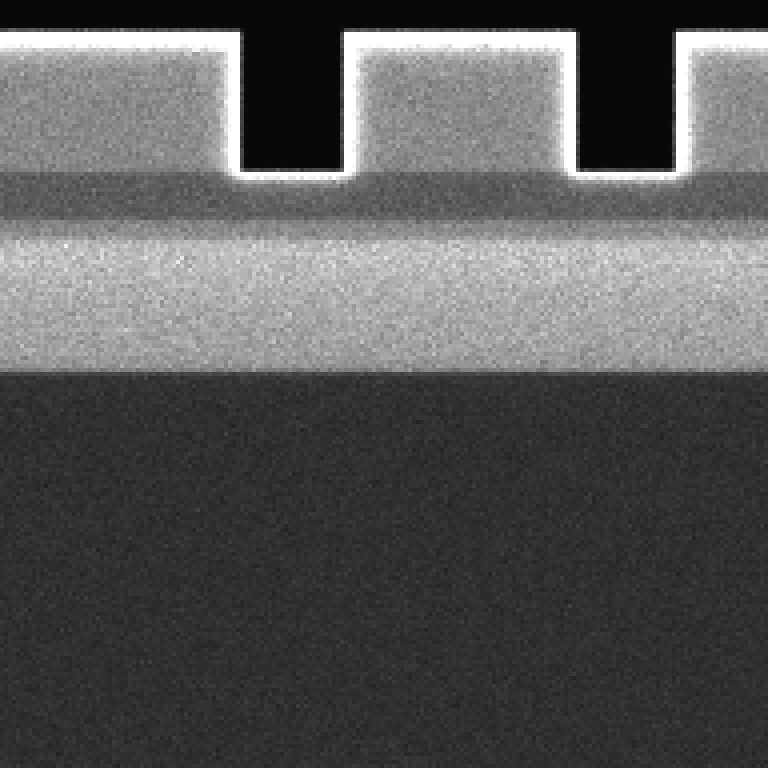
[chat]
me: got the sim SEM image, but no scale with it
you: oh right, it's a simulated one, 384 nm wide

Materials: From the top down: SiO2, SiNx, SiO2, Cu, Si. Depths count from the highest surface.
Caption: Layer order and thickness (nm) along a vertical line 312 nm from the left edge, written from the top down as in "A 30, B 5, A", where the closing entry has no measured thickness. empty 70, SiNx 24, SiO2 10, Cu 66, Si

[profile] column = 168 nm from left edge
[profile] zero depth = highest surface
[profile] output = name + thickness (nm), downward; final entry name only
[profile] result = empty 70, SiNx 24, SiO2 10, Cu 66, Si